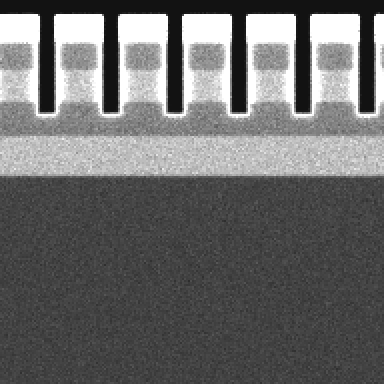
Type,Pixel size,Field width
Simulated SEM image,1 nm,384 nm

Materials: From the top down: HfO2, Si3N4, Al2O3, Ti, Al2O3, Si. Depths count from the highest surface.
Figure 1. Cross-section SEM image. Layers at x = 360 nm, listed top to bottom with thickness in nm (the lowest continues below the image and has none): empty 98, Ti 22, Al2O3 40, Si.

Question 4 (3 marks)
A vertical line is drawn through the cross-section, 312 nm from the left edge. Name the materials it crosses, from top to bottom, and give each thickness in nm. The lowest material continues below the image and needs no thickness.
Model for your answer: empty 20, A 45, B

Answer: HfO2 26, Si3N4 28, Al2O3 32, Ti 34, Al2O3 40, Si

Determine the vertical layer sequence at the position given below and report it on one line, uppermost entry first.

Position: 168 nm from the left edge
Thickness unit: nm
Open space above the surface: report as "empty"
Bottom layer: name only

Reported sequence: empty 98, Ti 22, Al2O3 40, Si